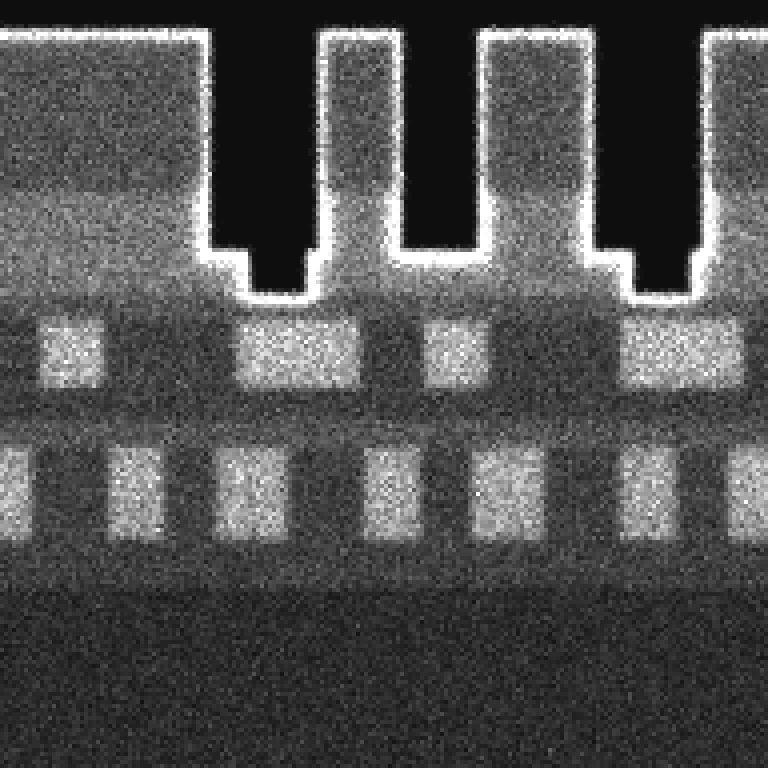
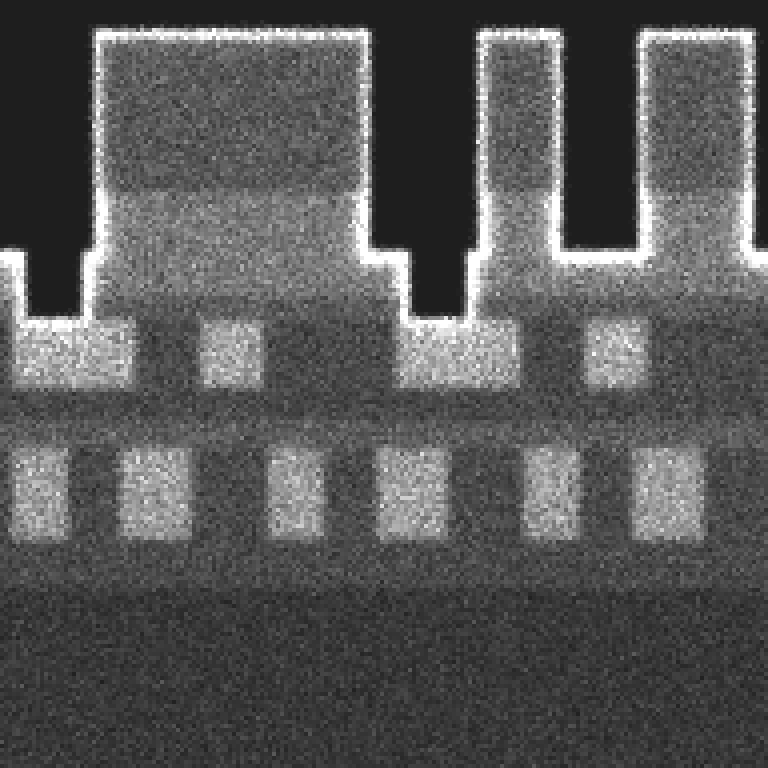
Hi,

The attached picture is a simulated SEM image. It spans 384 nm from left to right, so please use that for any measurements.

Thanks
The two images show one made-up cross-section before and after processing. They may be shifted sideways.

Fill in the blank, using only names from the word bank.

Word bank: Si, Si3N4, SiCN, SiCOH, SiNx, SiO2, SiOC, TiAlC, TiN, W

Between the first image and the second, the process removed Si3N4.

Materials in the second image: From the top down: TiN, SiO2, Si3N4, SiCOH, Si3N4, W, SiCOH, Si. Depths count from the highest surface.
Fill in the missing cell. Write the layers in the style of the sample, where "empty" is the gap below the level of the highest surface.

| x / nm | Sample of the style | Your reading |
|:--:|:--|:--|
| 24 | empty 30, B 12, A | empty 144, W 34, SiCOH 16, Si3N4 14, W 46, SiCOH 24, Si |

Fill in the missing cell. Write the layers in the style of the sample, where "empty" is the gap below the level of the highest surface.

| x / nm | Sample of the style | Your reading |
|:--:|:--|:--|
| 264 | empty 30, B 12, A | TiN 80, SiO2 52, Si3N4 12, SiCOH 50, Si3N4 14, W 46, SiCOH 24, Si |